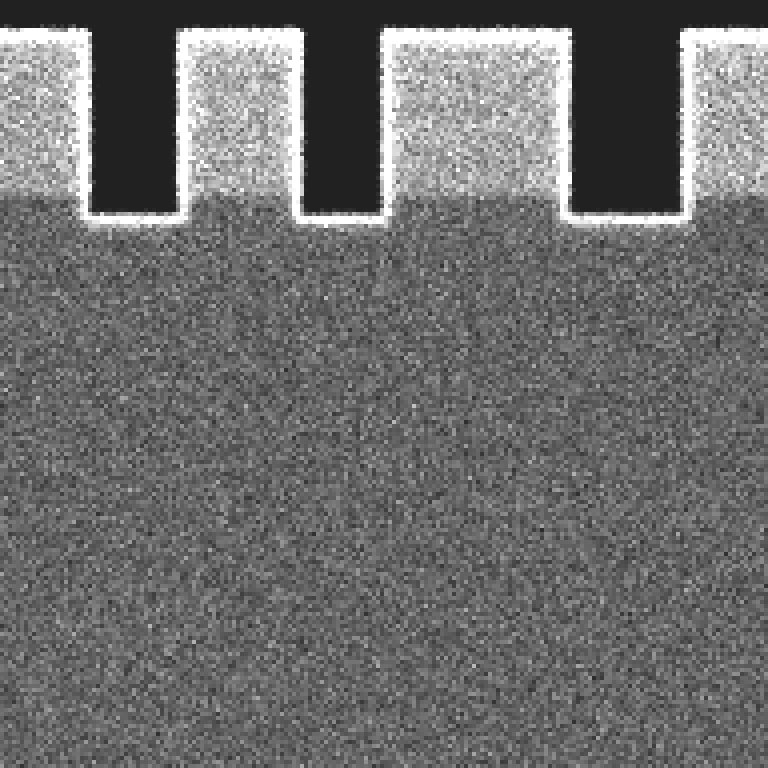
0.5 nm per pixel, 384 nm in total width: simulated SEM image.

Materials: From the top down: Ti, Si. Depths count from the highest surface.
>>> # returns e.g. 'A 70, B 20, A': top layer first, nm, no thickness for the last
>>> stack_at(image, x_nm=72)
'empty 92, Si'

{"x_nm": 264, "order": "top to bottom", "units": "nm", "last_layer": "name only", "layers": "Ti 82, Si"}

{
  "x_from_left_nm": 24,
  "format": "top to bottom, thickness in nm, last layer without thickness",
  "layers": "Ti 82, Si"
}